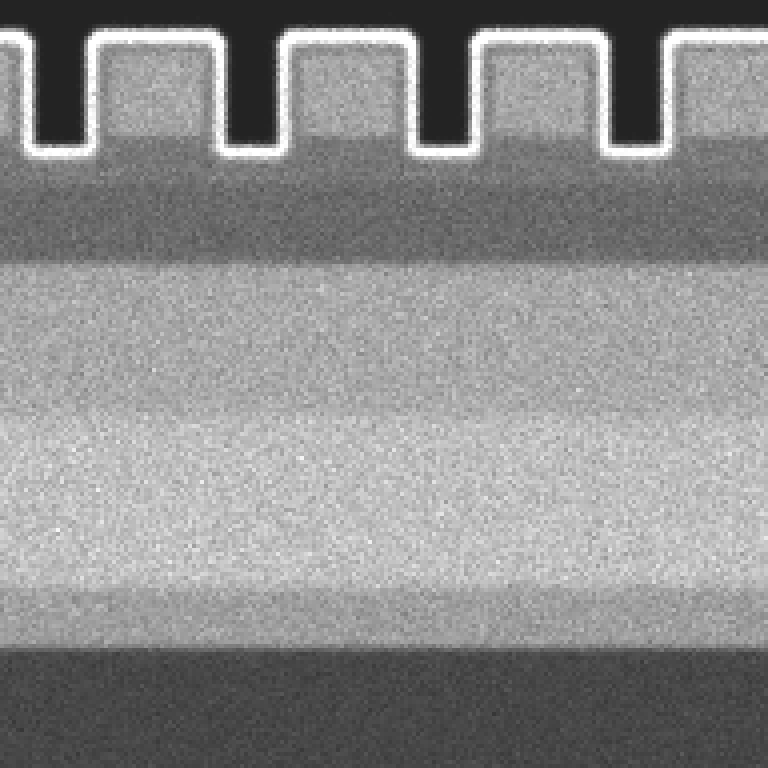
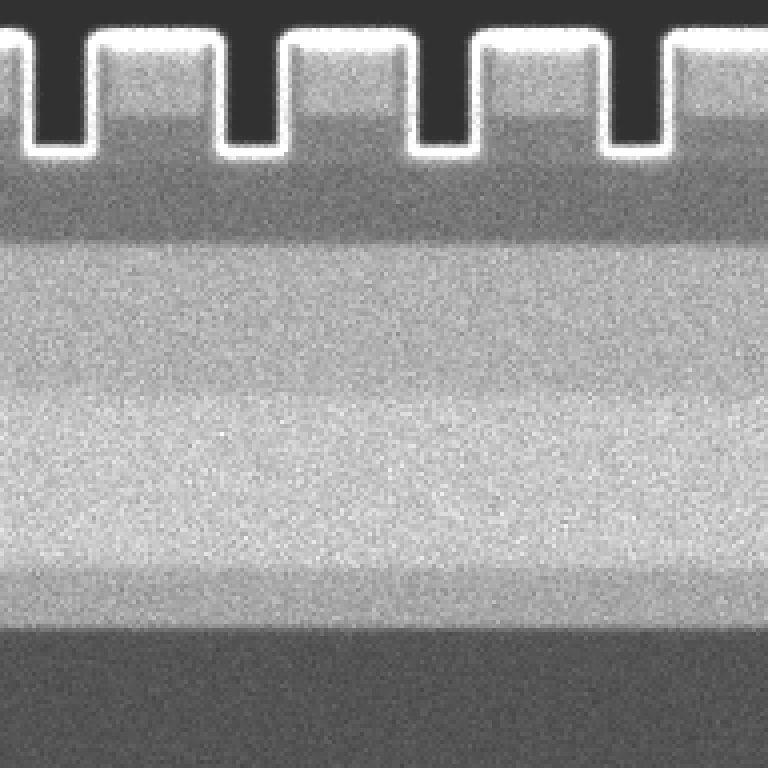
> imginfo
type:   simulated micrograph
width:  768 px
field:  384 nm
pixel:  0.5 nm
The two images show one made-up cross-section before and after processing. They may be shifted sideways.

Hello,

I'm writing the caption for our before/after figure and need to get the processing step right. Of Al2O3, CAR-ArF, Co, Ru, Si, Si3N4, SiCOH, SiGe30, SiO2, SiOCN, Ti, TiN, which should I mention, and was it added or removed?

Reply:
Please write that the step removed SiOCN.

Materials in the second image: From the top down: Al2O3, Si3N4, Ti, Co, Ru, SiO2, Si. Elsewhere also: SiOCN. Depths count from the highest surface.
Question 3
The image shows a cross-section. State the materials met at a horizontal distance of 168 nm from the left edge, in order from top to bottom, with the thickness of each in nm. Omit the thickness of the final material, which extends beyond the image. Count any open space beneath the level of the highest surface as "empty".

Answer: Al2O3 42, Si3N4 24, Ti 40, Co 76, Ru 86, SiO2 30, Si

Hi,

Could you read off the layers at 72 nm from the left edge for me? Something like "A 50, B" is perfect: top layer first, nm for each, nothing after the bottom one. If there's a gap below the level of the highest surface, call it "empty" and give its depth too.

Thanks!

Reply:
Al2O3 42, Si3N4 24, Ti 40, Co 76, Ru 86, SiO2 30, Si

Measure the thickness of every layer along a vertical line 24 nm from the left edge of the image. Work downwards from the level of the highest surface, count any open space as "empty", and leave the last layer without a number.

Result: empty 58, Si3N4 8, Ti 40, Co 76, Ru 86, SiO2 30, Si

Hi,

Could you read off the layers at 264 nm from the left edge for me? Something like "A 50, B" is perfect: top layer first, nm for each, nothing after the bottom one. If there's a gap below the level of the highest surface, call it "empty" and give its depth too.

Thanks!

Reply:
Al2O3 42, Si3N4 24, Ti 40, Co 76, Ru 86, SiO2 30, Si